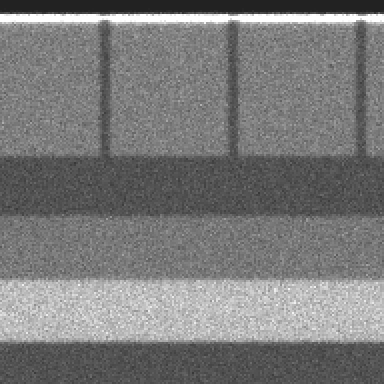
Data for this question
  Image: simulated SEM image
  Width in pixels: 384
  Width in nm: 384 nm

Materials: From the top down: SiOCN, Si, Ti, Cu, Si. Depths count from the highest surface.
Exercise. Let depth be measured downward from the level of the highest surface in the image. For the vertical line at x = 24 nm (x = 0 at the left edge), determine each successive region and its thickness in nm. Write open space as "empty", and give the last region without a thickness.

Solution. SiOCN 140, Si 60, Ti 64, Cu 62, Si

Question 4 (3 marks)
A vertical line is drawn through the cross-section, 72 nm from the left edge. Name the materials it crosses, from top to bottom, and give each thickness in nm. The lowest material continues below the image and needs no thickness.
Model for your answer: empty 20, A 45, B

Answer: SiOCN 140, Si 60, Ti 64, Cu 62, Si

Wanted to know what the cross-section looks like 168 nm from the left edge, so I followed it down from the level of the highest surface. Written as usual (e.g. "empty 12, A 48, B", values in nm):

SiOCN 140, Si 60, Ti 64, Cu 62, Si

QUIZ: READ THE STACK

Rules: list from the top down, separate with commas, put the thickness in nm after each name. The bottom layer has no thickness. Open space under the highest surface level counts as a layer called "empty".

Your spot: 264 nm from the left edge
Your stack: SiOCN 140, Si 60, Ti 64, Cu 62, Si